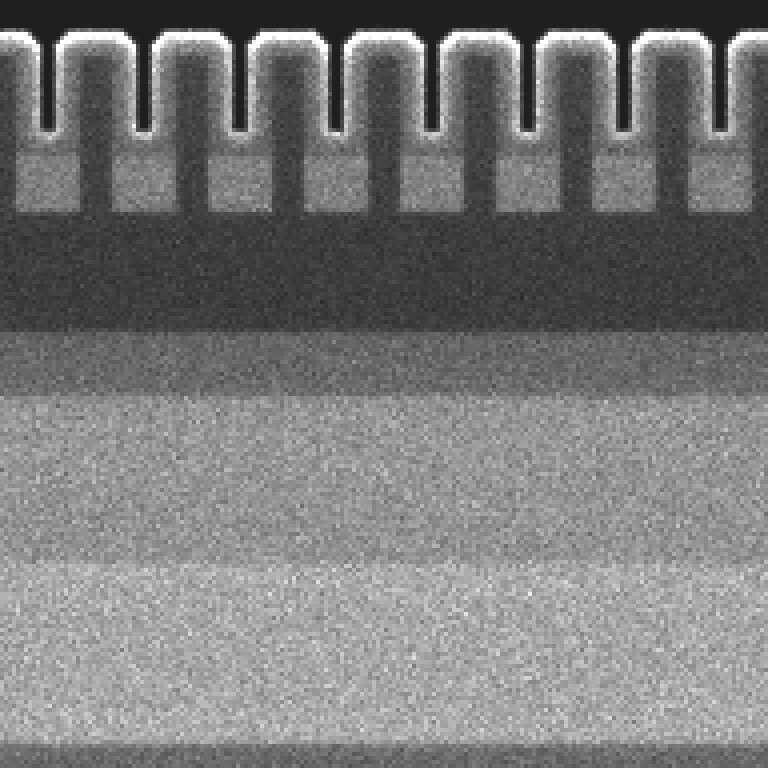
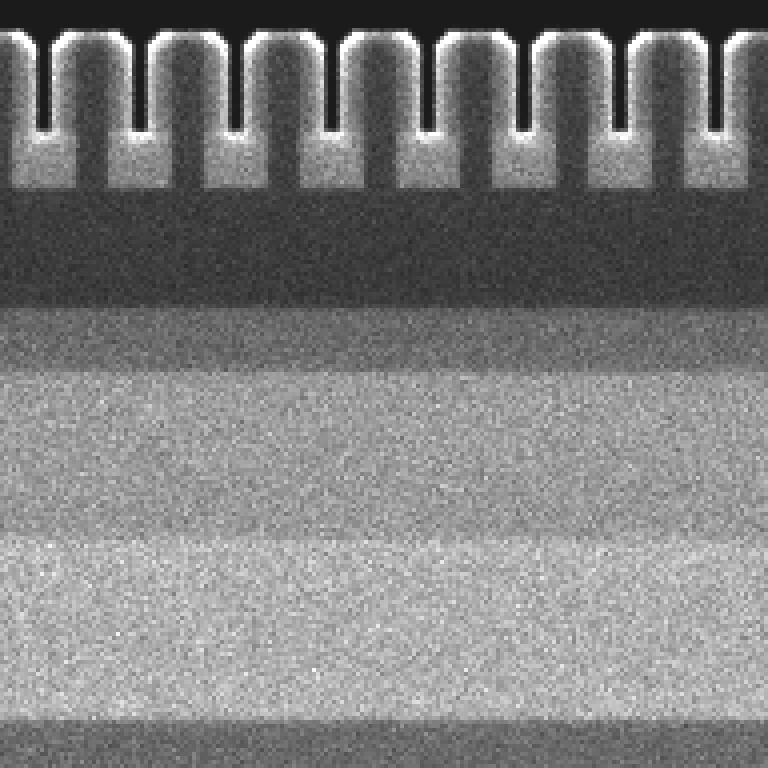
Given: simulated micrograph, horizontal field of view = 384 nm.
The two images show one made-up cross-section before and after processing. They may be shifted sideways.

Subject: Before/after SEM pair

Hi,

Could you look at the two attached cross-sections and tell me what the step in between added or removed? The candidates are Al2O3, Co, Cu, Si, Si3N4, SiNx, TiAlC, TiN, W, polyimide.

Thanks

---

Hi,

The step removed Si3N4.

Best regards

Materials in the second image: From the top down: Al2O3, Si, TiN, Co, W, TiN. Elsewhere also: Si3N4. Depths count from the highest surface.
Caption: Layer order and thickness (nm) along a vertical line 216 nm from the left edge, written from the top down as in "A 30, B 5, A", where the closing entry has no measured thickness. empty 50, Al2O3 28, Si 60, TiN 32, Co 84, W 90, TiN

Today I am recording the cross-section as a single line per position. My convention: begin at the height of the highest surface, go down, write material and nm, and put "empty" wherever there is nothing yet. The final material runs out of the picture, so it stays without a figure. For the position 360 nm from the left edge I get empty 50, Al2O3 28, Si 60, TiN 32, Co 84, W 90, TiN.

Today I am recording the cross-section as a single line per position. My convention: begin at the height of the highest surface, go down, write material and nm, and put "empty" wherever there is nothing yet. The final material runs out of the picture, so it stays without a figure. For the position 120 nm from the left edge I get empty 50, Al2O3 28, Si 60, TiN 32, Co 84, W 90, TiN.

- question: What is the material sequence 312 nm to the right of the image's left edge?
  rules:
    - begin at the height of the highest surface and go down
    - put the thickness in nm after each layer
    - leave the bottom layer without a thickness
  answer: empty 50, Al2O3 28, Si 60, TiN 32, Co 84, W 90, TiN